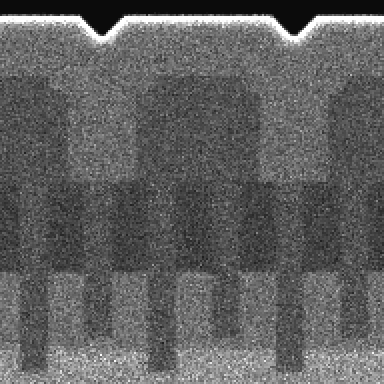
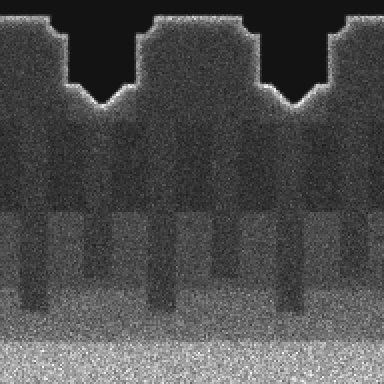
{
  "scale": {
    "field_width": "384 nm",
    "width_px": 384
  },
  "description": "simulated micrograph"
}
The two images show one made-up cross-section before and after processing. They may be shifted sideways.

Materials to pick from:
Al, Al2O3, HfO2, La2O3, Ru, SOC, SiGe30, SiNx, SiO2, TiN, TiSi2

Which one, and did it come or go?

SiO2 - removed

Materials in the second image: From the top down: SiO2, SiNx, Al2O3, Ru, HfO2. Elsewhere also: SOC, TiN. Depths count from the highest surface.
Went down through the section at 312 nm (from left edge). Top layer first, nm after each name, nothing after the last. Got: empty 72, SiO2 34, SiNx 90, Al2O3 78, Ru 52, HfO2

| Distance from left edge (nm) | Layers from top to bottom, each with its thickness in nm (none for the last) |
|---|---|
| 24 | SOC 106, TiN 190, Ru 30, HfO2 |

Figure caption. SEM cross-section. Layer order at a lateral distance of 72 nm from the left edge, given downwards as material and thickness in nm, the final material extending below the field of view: empty 68, SiO2 38, SiNx 90, Al2O3 78, Ru 52, HfO2